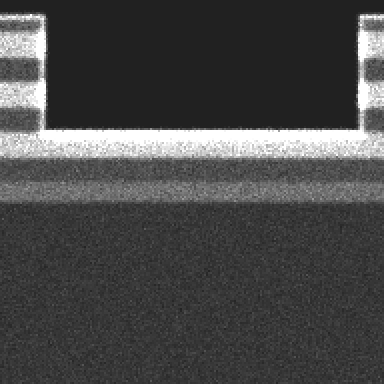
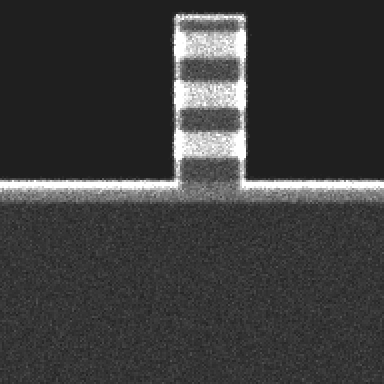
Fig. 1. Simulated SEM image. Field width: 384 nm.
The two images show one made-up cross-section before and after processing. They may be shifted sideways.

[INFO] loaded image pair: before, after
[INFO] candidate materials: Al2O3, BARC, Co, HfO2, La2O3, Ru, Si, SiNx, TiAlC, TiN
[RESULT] removed HfO2 and SiNx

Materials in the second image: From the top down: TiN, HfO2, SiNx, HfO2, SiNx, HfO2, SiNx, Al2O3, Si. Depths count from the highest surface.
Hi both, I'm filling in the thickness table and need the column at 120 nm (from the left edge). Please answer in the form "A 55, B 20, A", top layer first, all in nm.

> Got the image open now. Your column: empty 166, Al2O3 20, Si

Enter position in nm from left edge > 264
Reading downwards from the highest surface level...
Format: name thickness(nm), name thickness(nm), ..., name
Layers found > empty 166, Al2O3 20, Si